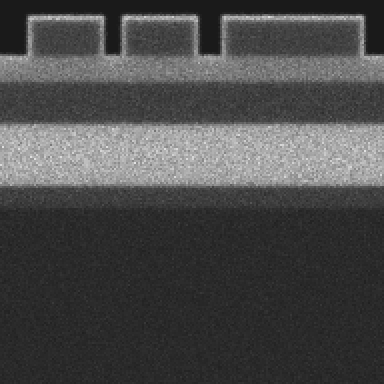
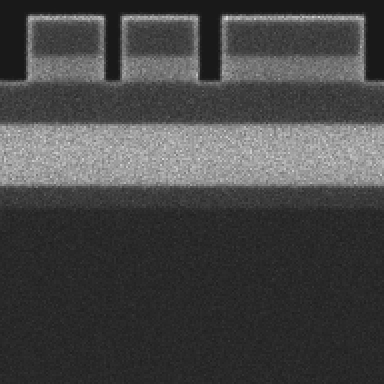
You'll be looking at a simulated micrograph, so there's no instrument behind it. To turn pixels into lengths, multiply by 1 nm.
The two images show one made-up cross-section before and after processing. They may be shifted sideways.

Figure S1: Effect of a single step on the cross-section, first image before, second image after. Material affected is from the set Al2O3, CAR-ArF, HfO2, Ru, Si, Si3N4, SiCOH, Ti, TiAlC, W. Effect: removed W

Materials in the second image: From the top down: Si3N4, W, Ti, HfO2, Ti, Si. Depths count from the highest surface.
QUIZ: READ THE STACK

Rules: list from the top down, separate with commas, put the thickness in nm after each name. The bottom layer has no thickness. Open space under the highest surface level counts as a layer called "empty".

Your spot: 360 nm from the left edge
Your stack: Si3N4 40, W 26, Ti 42, HfO2 62, Ti 22, Si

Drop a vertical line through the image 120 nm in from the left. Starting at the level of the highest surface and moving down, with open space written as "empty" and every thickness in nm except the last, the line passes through empty 66, Ti 42, HfO2 62, Ti 22, Si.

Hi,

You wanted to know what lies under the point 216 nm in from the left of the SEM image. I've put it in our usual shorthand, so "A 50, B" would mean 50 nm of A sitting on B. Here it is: empty 66, Ti 42, HfO2 62, Ti 22, Si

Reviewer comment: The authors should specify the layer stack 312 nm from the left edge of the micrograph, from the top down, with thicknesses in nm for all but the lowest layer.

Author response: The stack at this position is Si3N4 40, W 26, Ti 42, HfO2 62, Ti 22, Si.